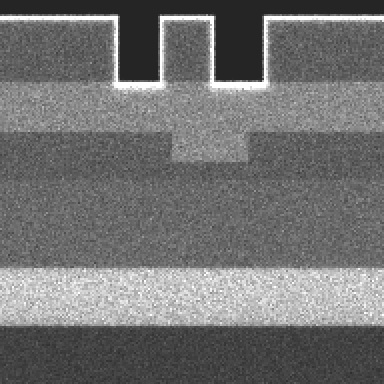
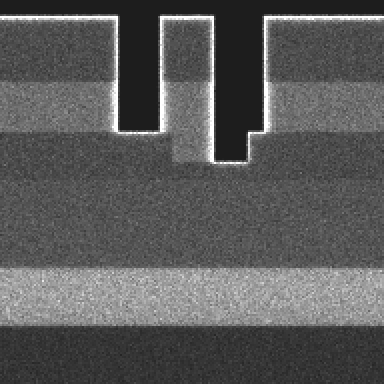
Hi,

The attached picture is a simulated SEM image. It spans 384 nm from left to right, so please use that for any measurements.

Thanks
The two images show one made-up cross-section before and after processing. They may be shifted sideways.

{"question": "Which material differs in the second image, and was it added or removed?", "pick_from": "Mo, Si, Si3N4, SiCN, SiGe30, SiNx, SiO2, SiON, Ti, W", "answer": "SiO2, removed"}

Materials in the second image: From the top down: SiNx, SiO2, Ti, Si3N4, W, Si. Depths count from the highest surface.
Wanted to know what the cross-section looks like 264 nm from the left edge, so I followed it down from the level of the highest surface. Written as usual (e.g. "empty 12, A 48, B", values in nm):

SiNx 66, SiO2 50, Ti 48, Si3N4 88, W 58, Si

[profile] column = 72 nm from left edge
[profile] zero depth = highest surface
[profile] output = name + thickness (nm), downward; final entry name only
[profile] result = SiNx 66, SiO2 50, Ti 48, Si3N4 88, W 58, Si